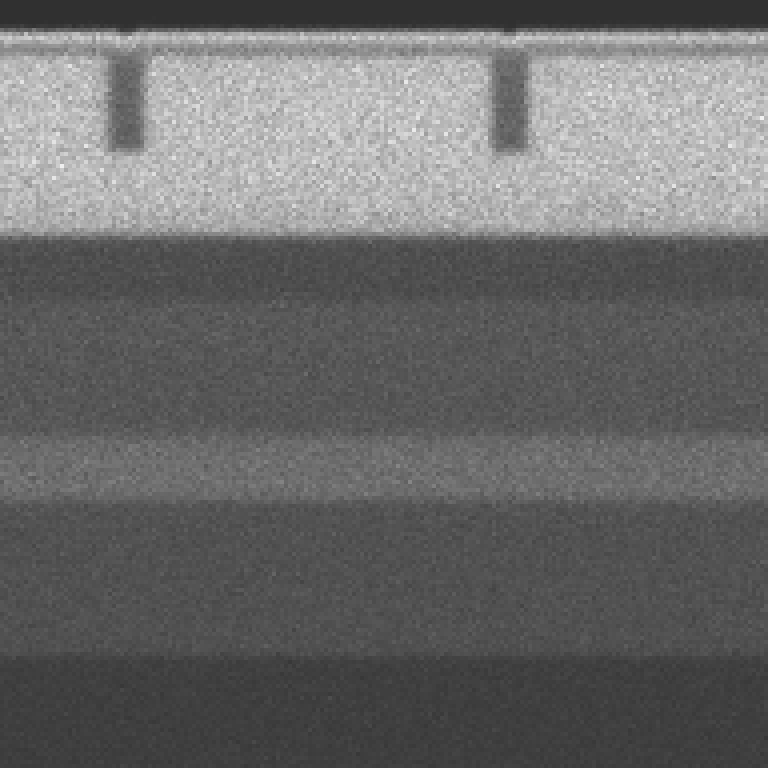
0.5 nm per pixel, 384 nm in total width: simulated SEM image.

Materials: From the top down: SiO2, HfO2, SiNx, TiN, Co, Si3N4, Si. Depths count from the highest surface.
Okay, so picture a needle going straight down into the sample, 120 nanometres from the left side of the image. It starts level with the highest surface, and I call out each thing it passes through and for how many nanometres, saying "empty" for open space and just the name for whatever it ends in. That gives SiO2 12, HfO2 90, SiNx 32, TiN 68, Co 32, Si3N4 78, Si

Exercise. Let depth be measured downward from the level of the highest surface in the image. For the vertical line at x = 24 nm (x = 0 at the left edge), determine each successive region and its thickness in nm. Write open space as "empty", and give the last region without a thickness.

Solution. SiO2 12, HfO2 90, SiNx 32, TiN 68, Co 32, Si3N4 78, Si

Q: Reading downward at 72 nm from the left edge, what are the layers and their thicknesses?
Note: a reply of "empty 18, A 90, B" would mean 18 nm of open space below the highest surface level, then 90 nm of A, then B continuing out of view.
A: SiO2 12, HfO2 90, SiNx 32, TiN 68, Co 32, Si3N4 78, Si